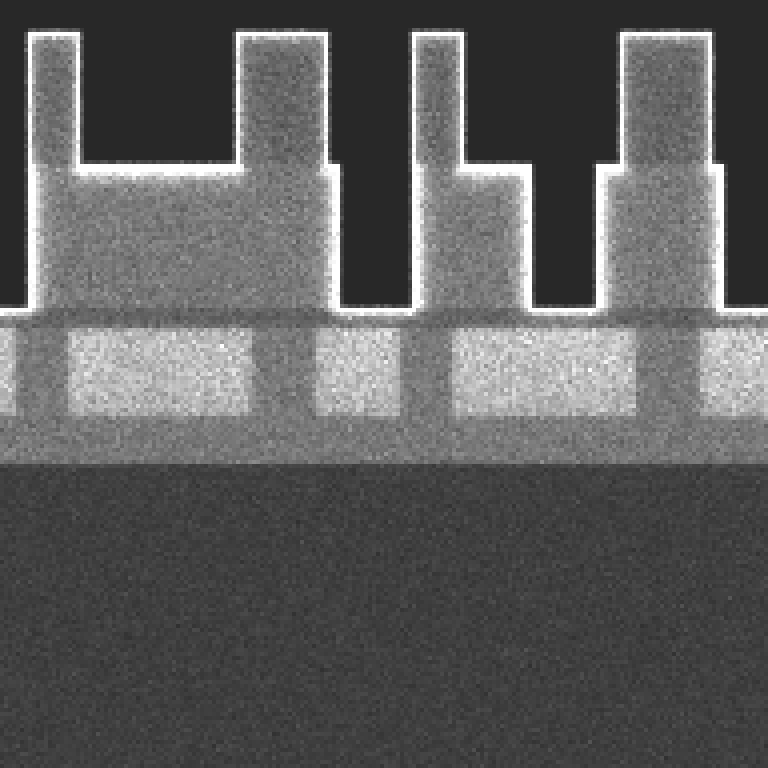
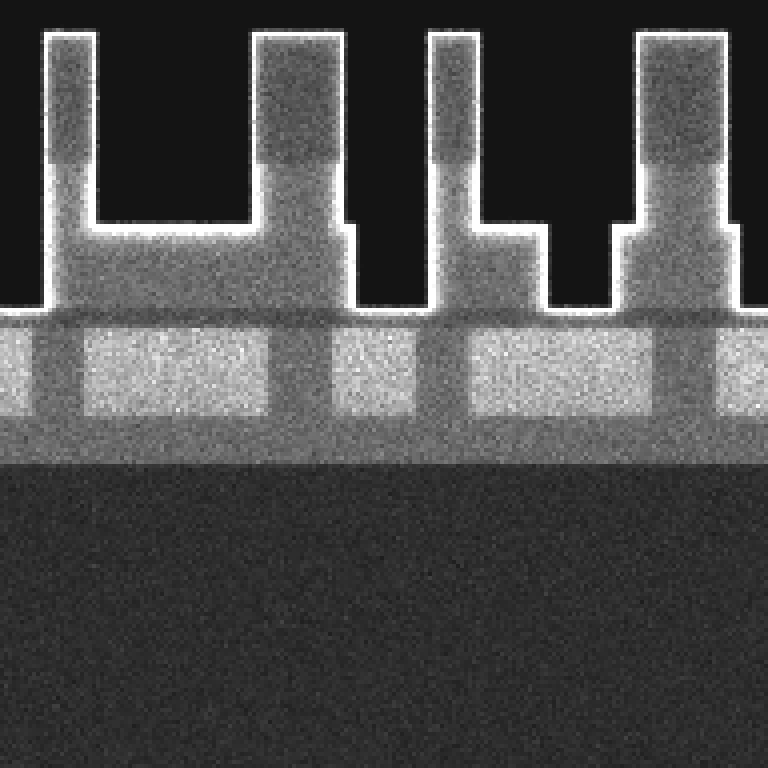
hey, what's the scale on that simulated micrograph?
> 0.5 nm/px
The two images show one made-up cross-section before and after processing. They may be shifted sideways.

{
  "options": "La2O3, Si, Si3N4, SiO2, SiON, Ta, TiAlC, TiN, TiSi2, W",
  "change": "removed",
  "material": "SiO2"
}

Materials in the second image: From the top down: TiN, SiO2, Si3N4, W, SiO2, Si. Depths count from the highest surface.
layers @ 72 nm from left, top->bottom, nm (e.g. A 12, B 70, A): empty 96, SiO2 42, Si3N4 10, W 44, SiO2 24, Si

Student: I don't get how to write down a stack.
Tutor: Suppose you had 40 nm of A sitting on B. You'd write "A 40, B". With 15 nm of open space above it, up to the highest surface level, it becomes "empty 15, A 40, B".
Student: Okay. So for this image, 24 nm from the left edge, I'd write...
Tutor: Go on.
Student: TiN 66, SiO2 72, Si3N4 10, SiO2 68, Si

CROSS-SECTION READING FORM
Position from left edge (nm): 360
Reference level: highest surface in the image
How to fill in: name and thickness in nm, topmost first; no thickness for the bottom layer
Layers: TiN 66, SiO2 72, Si3N4 10, W 44, SiO2 24, Si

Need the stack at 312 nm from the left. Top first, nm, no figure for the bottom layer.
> empty 96, SiO2 42, Si3N4 10, W 44, SiO2 24, Si